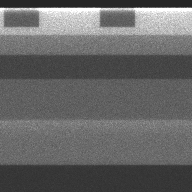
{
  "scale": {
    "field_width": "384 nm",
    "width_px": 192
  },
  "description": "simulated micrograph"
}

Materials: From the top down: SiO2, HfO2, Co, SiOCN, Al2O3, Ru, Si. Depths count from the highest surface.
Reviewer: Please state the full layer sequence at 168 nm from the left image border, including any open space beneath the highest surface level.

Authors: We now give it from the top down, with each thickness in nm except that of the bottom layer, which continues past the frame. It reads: HfO2 54, Co 40, SiOCN 48, Al2O3 82, Ru 90, Si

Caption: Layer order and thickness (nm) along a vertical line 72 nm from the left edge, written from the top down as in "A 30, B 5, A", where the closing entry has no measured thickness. SiO2 38, HfO2 16, Co 40, SiOCN 48, Al2O3 82, Ru 90, Si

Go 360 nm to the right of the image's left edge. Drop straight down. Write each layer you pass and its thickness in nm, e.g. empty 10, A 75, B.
HfO2 54, Co 40, SiOCN 48, Al2O3 82, Ru 90, Si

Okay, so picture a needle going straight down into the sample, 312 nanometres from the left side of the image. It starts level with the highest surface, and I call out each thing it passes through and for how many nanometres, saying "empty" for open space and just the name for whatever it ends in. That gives HfO2 54, Co 40, SiOCN 48, Al2O3 82, Ru 90, Si